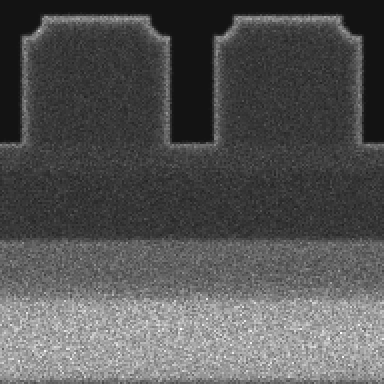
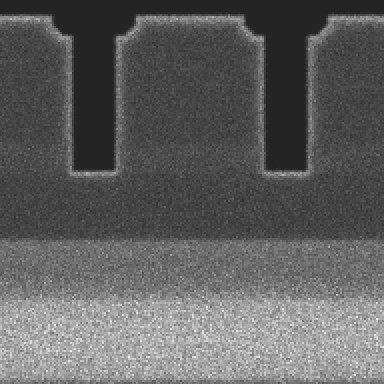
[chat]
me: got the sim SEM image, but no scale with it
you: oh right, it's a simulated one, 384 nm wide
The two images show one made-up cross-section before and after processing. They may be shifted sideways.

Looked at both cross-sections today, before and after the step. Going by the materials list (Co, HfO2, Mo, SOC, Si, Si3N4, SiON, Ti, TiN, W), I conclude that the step removed TiN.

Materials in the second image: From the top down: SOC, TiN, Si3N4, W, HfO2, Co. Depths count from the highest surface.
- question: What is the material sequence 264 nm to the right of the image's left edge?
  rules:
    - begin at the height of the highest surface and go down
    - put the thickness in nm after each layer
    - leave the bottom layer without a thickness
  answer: empty 156, Si3N4 68, W 60, HfO2 80, Co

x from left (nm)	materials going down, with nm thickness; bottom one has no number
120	empty 20, SOC 108, TiN 28, Si3N4 68, W 60, HfO2 80, Co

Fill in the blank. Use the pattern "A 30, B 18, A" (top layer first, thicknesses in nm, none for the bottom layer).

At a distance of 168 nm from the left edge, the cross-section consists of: SOC 128, TiN 28, Si3N4 68, W 60, HfO2 80, Co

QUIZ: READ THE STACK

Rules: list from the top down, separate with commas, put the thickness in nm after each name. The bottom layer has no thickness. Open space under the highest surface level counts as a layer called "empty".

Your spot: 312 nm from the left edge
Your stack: empty 20, SOC 108, TiN 28, Si3N4 68, W 60, HfO2 80, Co